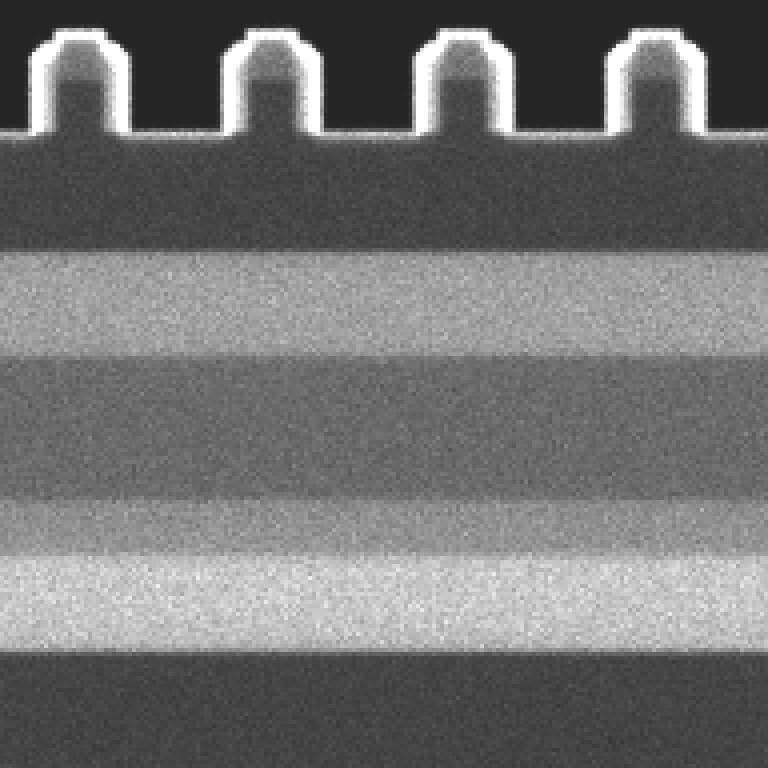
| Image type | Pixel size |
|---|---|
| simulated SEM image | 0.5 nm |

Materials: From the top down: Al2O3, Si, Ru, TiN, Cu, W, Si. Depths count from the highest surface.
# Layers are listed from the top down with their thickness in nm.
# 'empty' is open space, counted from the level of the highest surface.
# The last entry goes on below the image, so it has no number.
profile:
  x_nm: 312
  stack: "empty 6, Al2O3 44, Si 60, Ru 52, TiN 72, Cu 28, W 48, Si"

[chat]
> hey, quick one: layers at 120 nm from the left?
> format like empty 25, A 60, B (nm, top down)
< empty 6, Al2O3 44, Si 60, Ru 52, TiN 72, Cu 28, W 48, Si